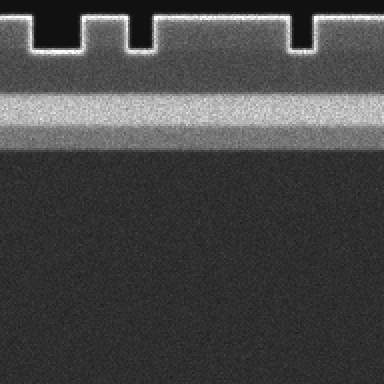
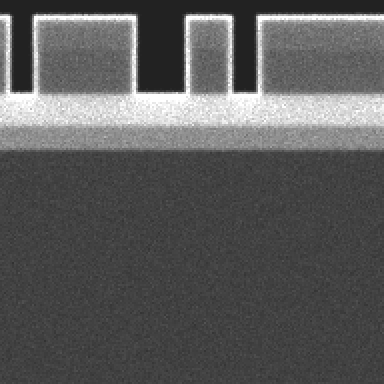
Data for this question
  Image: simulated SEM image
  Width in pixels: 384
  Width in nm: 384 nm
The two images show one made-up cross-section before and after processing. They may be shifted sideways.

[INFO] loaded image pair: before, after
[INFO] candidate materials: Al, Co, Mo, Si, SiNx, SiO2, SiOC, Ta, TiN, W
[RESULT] removed SiNx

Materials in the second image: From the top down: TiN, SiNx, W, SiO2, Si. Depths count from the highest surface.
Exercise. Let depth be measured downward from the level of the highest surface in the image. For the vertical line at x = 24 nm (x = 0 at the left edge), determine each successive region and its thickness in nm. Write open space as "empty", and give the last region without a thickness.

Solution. empty 78, W 32, SiO2 24, Si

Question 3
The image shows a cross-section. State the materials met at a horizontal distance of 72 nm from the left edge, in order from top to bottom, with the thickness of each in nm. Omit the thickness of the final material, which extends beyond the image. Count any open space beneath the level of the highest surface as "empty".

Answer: TiN 34, SiNx 44, W 32, SiO2 24, Si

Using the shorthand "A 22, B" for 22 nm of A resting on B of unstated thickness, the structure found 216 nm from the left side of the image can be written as TiN 34, SiNx 44, W 32, SiO2 24, Si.